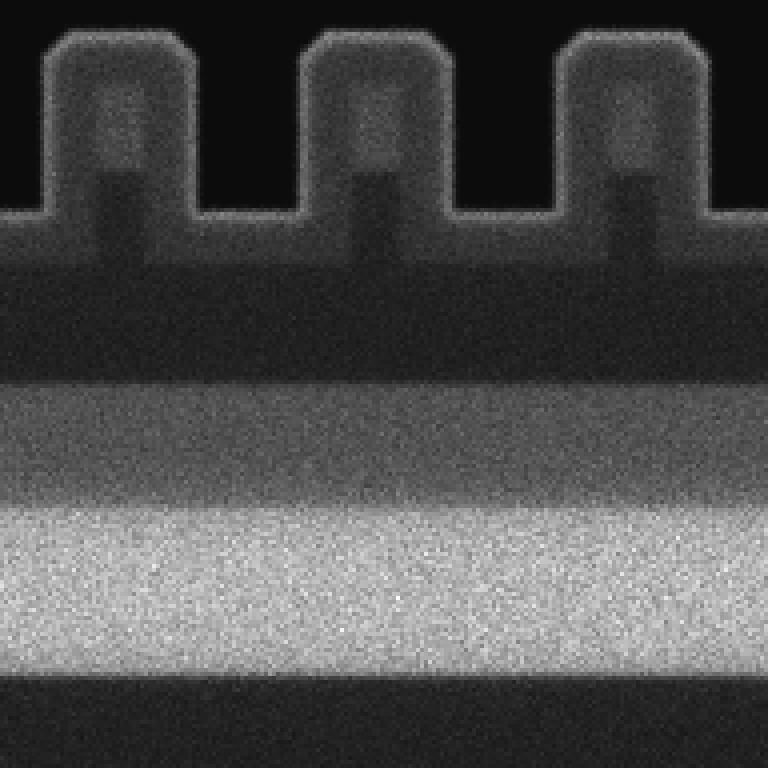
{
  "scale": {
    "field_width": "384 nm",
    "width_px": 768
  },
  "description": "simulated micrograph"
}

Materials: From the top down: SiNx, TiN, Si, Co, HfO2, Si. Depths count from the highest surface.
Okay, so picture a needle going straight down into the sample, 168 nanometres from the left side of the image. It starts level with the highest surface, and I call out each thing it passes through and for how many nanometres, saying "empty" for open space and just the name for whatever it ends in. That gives SiNx 116, Si 60, Co 62, HfO2 84, Si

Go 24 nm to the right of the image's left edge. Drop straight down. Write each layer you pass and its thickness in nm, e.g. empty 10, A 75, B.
empty 10, SiNx 106, Si 60, Co 62, HfO2 84, Si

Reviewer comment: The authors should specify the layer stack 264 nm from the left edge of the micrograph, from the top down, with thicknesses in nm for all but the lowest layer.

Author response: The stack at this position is empty 90, SiNx 26, Si 60, Co 62, HfO2 84, Si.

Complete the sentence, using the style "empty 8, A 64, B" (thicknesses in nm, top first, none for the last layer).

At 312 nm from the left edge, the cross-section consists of SiNx 26, TiN 44, Si 106, Co 62, HfO2 84, Si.